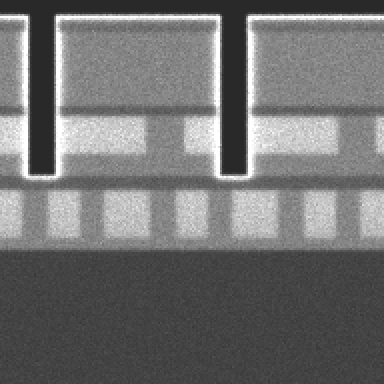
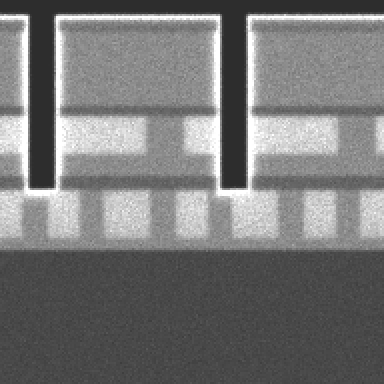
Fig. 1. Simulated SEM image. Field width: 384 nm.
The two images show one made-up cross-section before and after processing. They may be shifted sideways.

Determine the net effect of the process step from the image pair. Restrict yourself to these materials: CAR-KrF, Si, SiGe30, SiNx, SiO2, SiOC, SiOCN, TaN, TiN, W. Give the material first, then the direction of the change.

SiNx: removed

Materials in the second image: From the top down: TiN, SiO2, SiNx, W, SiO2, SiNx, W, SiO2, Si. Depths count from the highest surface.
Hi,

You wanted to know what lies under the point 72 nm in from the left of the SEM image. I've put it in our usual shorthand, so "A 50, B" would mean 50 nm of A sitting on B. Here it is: TiN 16, SiO2 74, SiNx 10, W 38, SiO2 22, SiNx 14, W 48, SiO2 12, Si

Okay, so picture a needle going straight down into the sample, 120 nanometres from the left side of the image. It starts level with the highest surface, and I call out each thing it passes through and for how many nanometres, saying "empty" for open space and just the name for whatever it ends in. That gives TiN 16, SiO2 74, SiNx 10, W 38, SiO2 22, SiNx 14, W 48, SiO2 12, Si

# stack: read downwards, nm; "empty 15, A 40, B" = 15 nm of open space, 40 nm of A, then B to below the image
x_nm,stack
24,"TiN 16, SiO2 74, SiNx 10, SiO2 60, SiNx 14, SiO2 60, Si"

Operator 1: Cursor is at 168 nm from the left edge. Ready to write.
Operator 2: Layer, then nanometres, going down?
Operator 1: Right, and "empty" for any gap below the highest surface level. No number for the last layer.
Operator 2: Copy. TiN 16, SiO2 74, SiNx 10, SiO2 60, SiNx 14, SiO2 60, Si